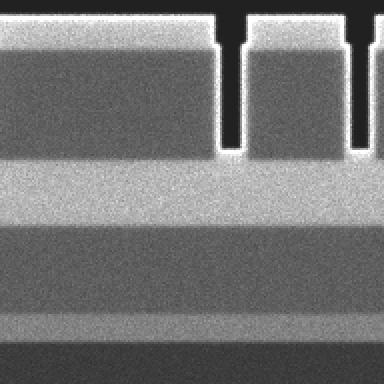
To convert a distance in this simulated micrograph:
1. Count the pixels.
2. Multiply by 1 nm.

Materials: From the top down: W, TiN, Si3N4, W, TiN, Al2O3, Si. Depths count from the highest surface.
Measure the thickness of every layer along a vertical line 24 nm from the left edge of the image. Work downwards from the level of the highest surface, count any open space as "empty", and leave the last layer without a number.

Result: W 34, TiN 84, Si3N4 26, W 66, TiN 88, Al2O3 28, Si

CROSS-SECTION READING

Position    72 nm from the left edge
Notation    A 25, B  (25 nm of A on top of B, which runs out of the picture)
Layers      W 34, TiN 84, Si3N4 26, W 66, TiN 88, Al2O3 28, Si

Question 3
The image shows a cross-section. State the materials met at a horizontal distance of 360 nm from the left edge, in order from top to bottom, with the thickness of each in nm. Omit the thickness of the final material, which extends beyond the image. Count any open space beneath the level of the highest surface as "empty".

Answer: empty 134, W 76, TiN 88, Al2O3 28, Si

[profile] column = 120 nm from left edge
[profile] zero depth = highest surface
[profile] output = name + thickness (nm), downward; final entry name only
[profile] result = W 34, TiN 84, Si3N4 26, W 66, TiN 88, Al2O3 28, Si